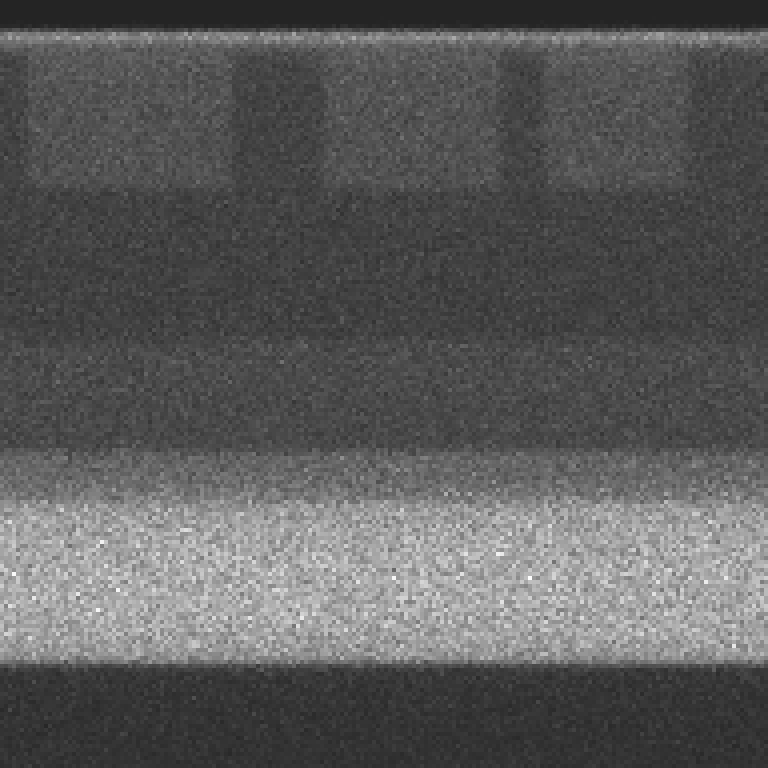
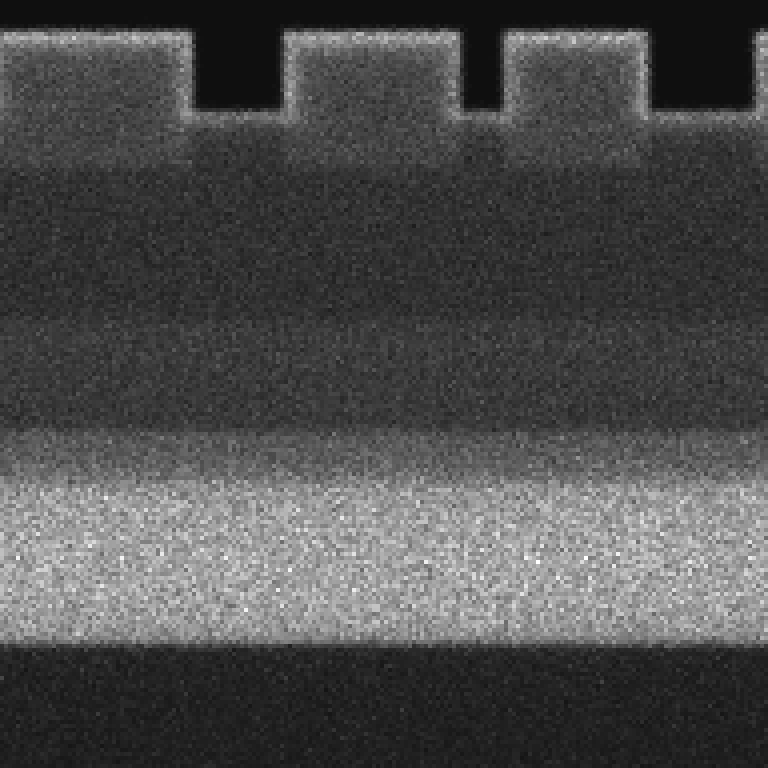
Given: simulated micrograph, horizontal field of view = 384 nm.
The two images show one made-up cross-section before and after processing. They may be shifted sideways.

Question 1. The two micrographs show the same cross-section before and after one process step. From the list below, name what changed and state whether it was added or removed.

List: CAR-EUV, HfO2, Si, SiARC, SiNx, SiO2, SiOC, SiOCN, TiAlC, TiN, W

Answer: SiARC, removed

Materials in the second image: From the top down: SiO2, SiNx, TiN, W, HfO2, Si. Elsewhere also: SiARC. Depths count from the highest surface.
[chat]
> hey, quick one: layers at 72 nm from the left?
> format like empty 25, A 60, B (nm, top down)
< SiO2 68, SiNx 76, TiN 56, W 26, HfO2 80, Si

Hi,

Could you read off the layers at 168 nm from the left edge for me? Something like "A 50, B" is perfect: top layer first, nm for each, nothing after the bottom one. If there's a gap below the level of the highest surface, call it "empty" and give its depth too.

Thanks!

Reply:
SiO2 68, SiNx 76, TiN 56, W 26, HfO2 80, Si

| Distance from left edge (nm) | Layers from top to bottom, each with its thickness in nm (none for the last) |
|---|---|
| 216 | SiO2 68, SiNx 76, TiN 56, W 26, HfO2 80, Si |